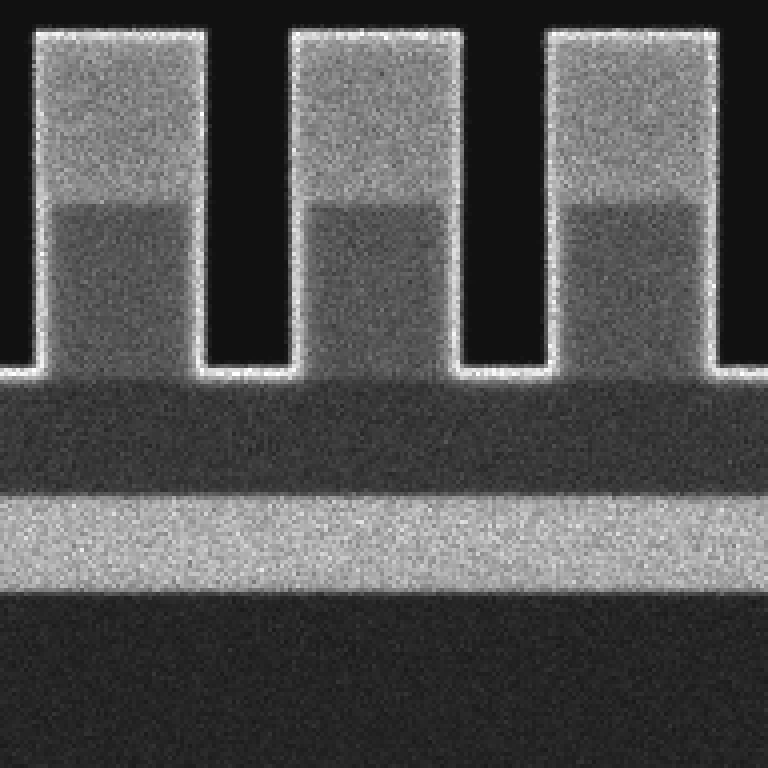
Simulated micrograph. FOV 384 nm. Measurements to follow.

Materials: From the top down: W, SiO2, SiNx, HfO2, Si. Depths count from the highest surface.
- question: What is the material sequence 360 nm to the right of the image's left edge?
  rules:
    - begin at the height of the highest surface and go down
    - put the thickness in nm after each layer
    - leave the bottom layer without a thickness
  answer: empty 168, SiO2 6, SiNx 58, HfO2 48, Si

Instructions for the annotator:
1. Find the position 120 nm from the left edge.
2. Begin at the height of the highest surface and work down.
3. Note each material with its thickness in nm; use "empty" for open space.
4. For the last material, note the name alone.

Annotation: empty 168, SiO2 6, SiNx 58, HfO2 48, Si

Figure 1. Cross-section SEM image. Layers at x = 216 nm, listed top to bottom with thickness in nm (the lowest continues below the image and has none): W 86, SiO2 88, SiNx 58, HfO2 48, Si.